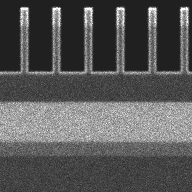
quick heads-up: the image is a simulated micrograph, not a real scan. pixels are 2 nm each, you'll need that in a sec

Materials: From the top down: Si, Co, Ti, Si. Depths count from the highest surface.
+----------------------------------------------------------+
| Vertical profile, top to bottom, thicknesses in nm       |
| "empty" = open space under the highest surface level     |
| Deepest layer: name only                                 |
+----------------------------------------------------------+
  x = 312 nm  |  empty 128, Si 60, Co 80, Ti 28, Si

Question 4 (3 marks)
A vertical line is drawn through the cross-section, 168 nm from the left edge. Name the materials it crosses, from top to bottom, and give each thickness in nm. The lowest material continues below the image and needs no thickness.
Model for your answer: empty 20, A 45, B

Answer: empty 128, Si 60, Co 80, Ti 28, Si